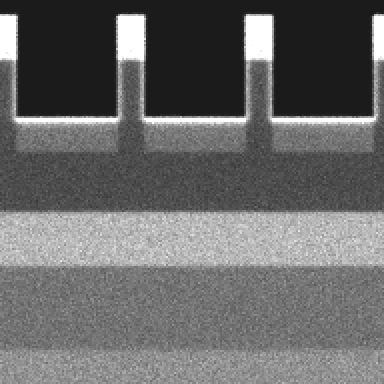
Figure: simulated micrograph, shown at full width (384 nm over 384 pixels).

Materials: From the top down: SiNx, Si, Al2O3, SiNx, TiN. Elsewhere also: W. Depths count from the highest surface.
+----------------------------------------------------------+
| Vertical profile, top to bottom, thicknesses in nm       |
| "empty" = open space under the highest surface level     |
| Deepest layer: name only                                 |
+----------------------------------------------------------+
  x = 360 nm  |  empty 102, SiNx 34, Si 60, Al2O3 54, SiNx 84, TiN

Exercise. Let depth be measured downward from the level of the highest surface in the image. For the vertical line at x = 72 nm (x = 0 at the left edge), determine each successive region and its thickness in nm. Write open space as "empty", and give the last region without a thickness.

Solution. empty 102, SiNx 34, Si 60, Al2O3 54, SiNx 84, TiN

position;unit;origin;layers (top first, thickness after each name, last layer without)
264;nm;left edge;W 44, Si 152, Al2O3 54, SiNx 84, TiN